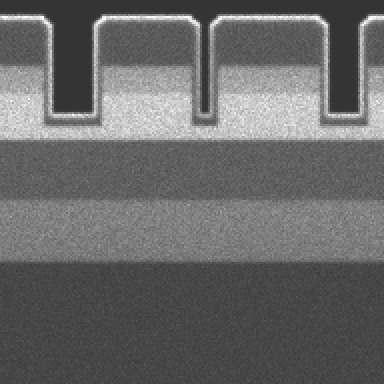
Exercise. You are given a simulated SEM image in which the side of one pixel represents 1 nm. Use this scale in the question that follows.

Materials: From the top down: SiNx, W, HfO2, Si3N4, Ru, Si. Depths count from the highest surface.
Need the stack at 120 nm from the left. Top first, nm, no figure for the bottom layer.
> SiNx 50, W 28, HfO2 46, Si3N4 60, Ru 62, Si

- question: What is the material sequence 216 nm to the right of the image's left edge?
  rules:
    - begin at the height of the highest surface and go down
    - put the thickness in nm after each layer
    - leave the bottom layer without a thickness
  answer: empty 4, SiNx 106, HfO2 14, Si3N4 60, Ru 62, Si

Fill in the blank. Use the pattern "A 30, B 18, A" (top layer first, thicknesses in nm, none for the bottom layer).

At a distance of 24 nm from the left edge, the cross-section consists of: SiNx 50, W 28, HfO2 46, Si3N4 60, Ru 62, Si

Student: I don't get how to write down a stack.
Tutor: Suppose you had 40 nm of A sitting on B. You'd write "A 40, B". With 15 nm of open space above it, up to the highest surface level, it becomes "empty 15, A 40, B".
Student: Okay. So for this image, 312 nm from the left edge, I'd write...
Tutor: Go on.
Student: SiNx 50, W 28, HfO2 46, Si3N4 60, Ru 62, Si